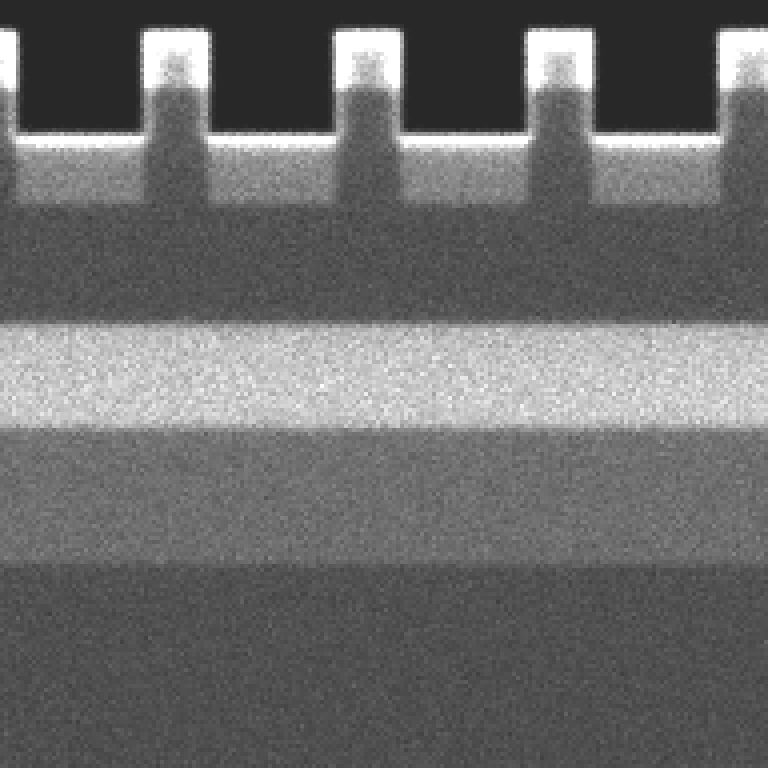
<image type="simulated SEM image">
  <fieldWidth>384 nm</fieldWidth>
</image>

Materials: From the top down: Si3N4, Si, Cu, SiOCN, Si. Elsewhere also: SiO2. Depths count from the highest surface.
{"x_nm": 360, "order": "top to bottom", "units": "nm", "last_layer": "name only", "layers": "SiO2 28, Si 118, Cu 52, SiOCN 68, Si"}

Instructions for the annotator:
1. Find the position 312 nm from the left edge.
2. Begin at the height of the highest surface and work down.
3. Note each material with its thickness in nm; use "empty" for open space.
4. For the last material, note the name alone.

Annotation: empty 52, Si3N4 34, Si 60, Cu 52, SiOCN 68, Si